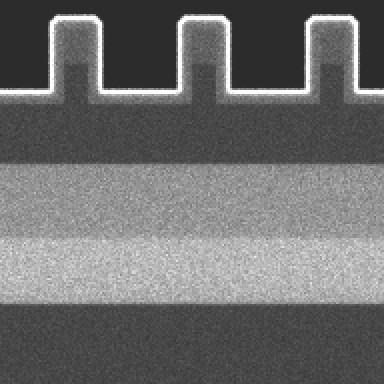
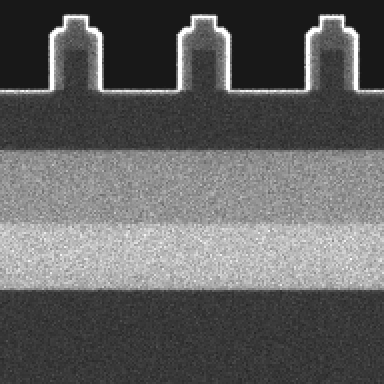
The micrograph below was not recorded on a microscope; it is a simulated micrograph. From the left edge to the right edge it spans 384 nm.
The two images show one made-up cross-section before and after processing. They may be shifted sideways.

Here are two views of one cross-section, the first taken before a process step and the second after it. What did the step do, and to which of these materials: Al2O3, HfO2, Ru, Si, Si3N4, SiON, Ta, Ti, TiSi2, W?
It removed Si3N4.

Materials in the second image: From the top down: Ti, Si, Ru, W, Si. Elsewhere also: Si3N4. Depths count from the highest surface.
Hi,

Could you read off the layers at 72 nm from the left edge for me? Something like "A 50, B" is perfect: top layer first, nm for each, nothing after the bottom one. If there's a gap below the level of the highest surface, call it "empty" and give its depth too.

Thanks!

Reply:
Ti 34, Si 100, Ru 74, W 66, Si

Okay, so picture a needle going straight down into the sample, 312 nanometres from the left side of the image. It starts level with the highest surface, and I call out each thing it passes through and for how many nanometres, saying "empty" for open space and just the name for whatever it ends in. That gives empty 12, Si3N4 62, Si 60, Ru 74, W 66, Si